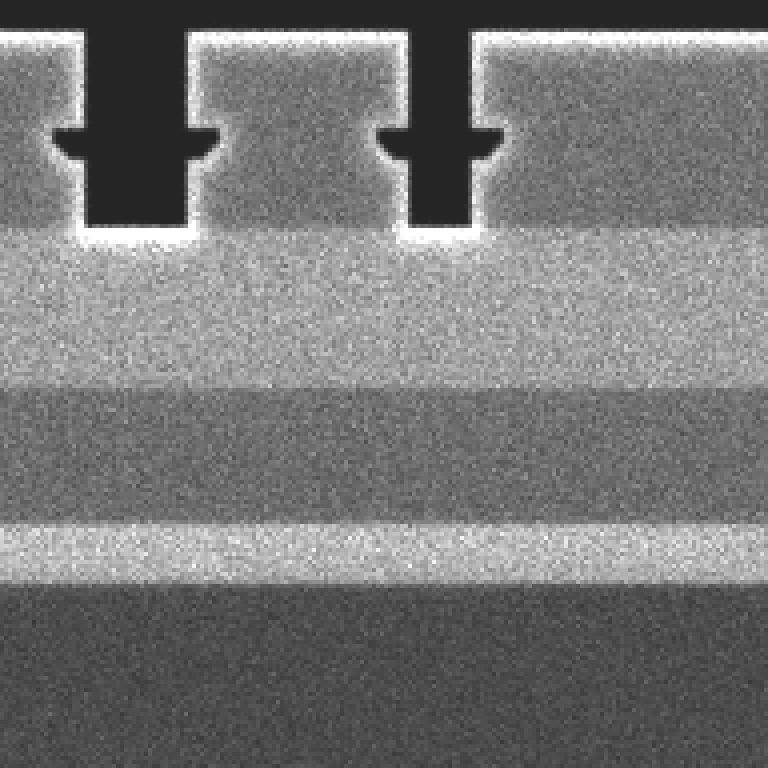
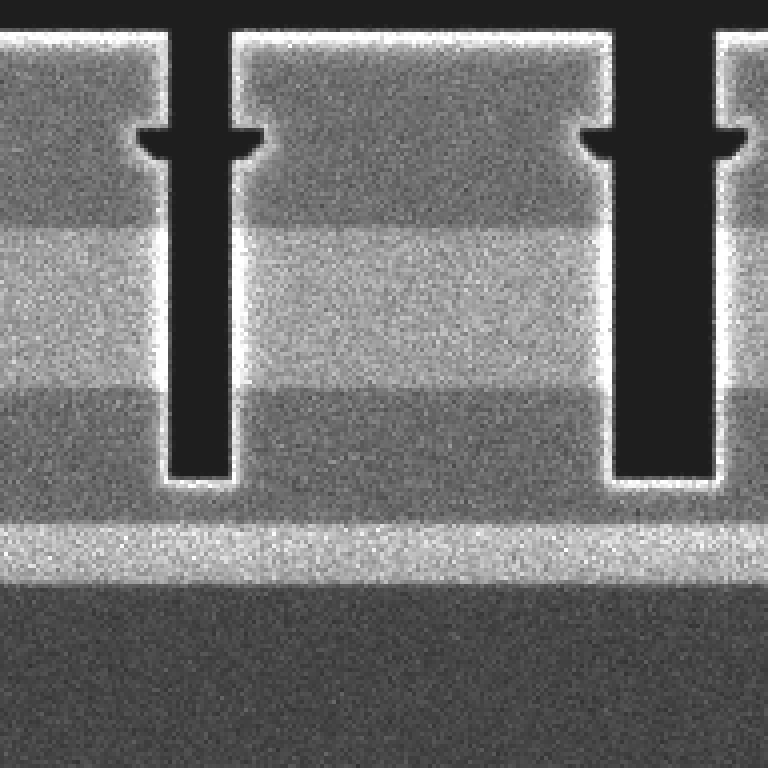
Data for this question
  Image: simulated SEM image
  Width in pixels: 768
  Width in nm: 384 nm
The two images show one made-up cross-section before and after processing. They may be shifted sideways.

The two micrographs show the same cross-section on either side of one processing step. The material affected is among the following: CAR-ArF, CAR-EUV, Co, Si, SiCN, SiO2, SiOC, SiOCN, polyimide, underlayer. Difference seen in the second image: SiO2 and SiOCN removed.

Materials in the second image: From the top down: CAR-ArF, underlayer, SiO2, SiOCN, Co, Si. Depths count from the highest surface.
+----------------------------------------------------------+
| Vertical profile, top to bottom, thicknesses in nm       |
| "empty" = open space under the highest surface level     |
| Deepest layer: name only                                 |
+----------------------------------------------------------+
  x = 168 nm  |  CAR-ArF 48, underlayer 50, SiO2 80, SiOCN 68, Co 30, Si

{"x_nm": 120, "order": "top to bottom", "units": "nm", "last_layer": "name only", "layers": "CAR-ArF 48, empty 16, underlayer 34, SiO2 80, SiOCN 68, Co 30, Si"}